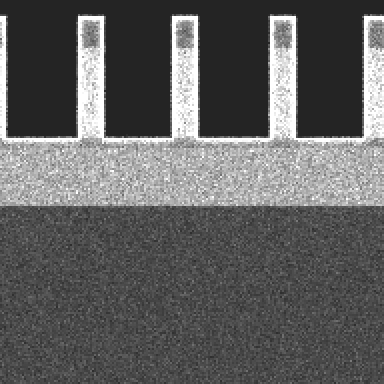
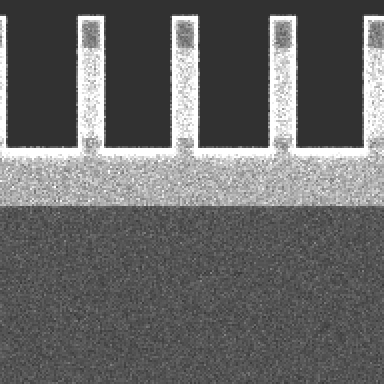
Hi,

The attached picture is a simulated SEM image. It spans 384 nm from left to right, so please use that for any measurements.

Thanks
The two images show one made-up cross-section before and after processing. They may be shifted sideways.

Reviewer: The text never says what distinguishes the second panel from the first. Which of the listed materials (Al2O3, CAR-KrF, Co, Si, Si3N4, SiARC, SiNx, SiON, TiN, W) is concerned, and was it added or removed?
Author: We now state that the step removed TiN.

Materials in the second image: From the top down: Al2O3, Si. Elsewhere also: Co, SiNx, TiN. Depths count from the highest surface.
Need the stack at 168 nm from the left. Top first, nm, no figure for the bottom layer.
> empty 132, Al2O3 58, Si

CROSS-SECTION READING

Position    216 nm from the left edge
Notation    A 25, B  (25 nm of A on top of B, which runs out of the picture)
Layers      empty 132, Al2O3 58, Si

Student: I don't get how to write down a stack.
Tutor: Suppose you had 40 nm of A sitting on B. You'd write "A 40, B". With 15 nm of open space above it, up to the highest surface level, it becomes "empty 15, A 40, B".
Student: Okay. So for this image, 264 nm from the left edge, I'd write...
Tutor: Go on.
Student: empty 132, Al2O3 58, Si